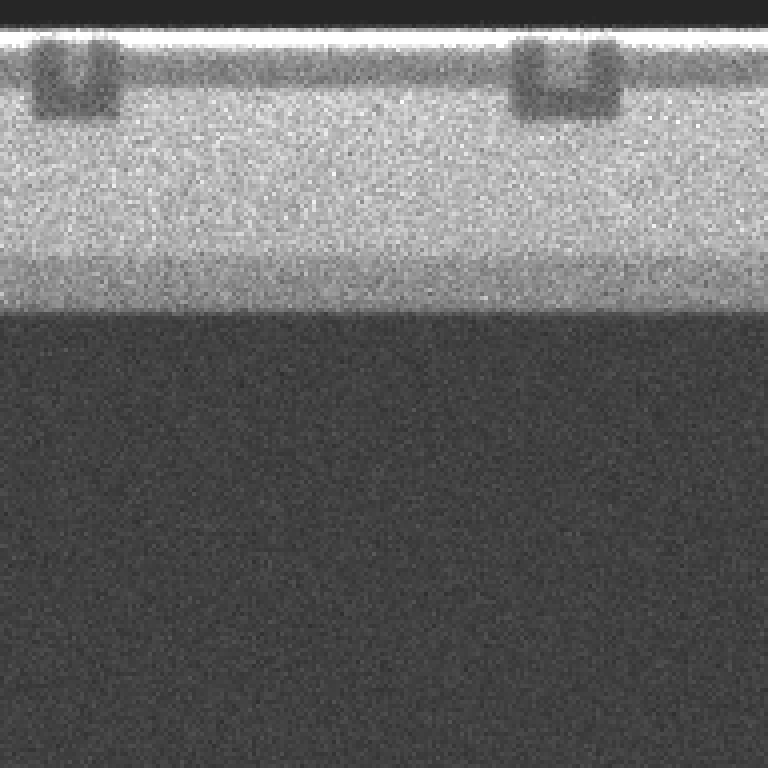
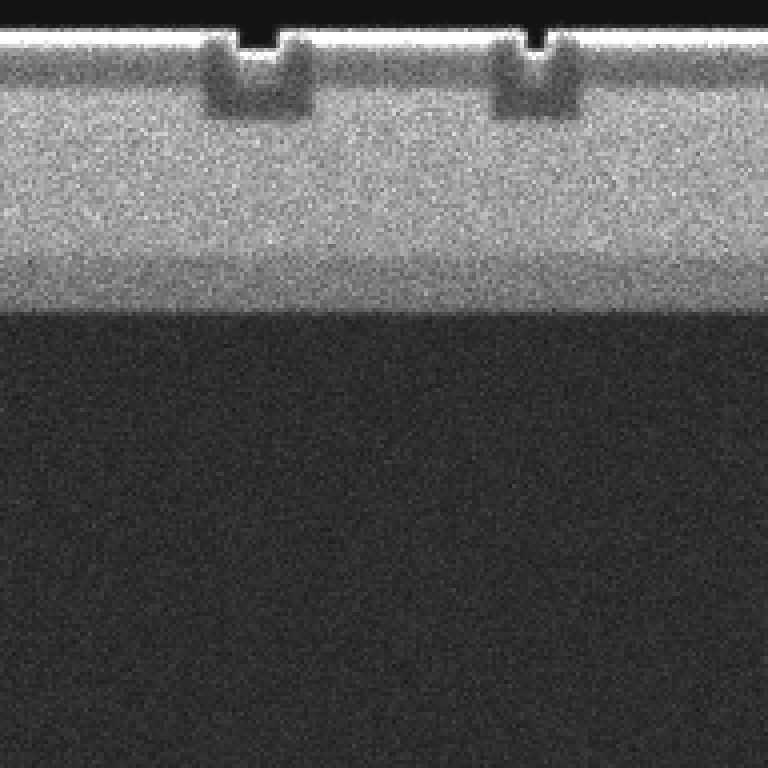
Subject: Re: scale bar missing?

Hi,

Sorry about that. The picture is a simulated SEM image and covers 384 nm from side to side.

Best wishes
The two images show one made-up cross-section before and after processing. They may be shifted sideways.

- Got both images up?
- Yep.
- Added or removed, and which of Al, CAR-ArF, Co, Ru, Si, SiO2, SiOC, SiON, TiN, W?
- removed, Co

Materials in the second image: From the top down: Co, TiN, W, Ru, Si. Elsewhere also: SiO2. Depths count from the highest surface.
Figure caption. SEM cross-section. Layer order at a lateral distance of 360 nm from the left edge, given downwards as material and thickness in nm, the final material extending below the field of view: SiO2 28, W 84, Ru 28, Si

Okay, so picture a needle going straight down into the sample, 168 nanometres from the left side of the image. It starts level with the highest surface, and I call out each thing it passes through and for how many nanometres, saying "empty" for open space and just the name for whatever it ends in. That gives SiO2 28, W 84, Ru 28, Si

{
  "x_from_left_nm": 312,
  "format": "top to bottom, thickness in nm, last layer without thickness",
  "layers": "SiO2 28, W 84, Ru 28, Si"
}